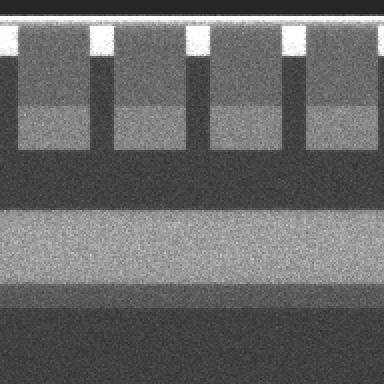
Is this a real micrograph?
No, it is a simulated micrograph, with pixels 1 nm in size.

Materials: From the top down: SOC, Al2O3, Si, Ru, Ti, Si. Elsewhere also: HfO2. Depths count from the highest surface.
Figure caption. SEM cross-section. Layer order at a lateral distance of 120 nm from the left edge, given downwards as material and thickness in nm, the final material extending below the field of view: SOC 90, Al2O3 44, Si 60, Ru 74, Ti 24, Si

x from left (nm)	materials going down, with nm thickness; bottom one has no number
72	SOC 90, Al2O3 44, Si 60, Ru 74, Ti 24, Si